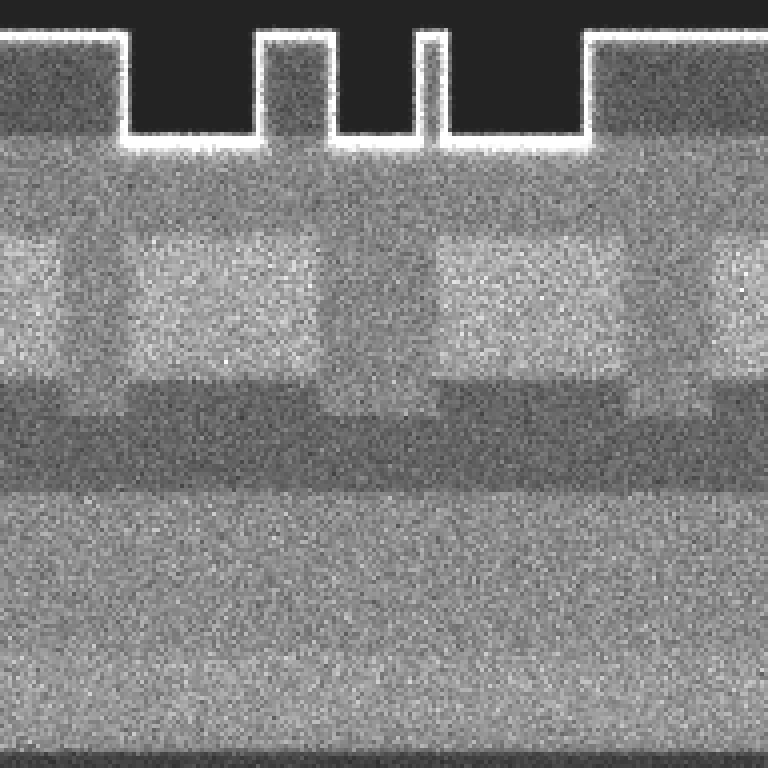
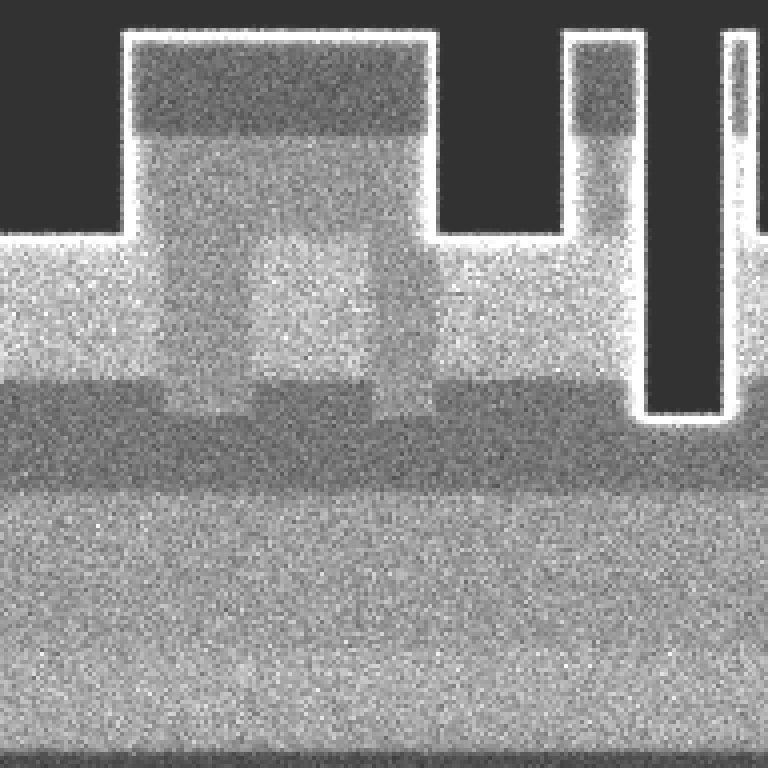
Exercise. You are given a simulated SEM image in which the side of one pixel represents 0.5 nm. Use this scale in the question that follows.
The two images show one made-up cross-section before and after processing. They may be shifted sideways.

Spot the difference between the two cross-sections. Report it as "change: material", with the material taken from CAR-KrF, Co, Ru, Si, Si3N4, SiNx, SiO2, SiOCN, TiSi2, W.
removed: SiO2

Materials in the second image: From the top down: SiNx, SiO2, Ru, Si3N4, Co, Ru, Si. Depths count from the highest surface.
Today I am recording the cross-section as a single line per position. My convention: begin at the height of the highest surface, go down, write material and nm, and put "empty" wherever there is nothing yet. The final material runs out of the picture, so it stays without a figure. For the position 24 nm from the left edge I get empty 102, Ru 72, Si3N4 56, Co 80, Ru 50, Si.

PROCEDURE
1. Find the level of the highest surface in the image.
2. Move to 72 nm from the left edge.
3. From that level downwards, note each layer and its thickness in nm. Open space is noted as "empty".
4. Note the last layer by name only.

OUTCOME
SiNx 52, SiO2 50, Ru 72, Si3N4 56, Co 80, Ru 50, Si